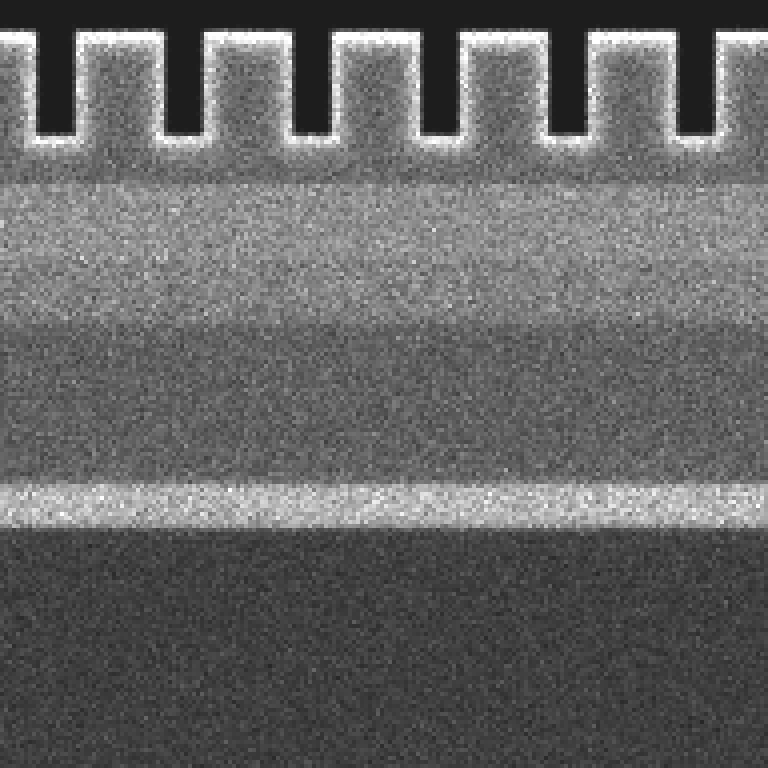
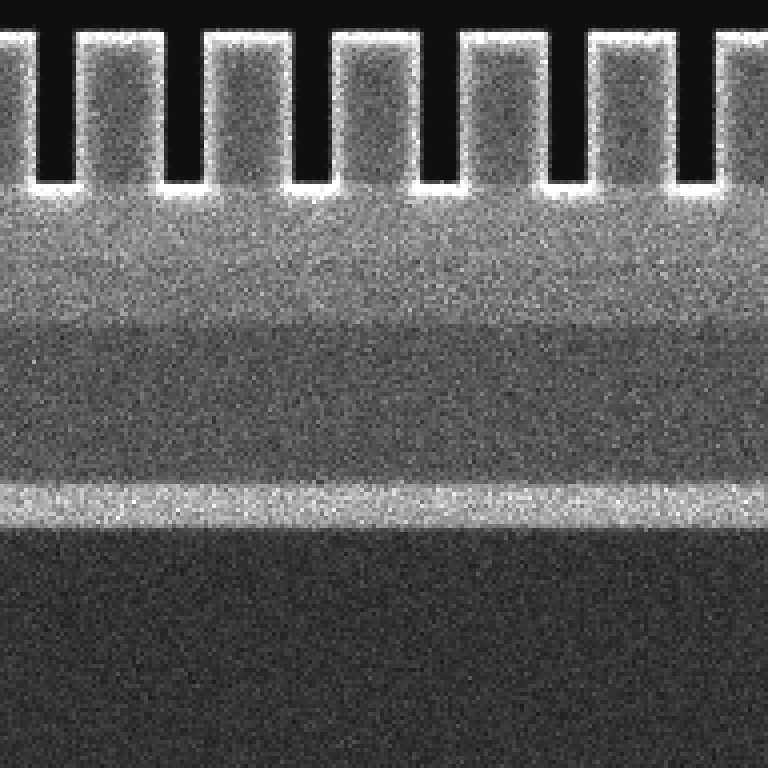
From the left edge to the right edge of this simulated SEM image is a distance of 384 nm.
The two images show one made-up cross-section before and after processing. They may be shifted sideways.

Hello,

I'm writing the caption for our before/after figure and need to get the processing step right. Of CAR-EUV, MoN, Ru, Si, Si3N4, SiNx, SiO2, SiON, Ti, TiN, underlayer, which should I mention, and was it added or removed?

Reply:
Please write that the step removed underlayer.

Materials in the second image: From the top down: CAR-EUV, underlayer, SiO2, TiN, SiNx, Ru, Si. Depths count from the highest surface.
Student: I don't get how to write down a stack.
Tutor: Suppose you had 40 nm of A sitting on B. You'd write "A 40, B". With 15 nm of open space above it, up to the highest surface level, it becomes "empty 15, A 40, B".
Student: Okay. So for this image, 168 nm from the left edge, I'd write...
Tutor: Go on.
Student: CAR-EUV 52, underlayer 24, SiO2 38, TiN 32, SiNx 80, Ru 22, Si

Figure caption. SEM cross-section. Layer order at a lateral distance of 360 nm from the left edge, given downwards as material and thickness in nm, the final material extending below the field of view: CAR-EUV 52, underlayer 24, SiO2 38, TiN 32, SiNx 80, Ru 22, Si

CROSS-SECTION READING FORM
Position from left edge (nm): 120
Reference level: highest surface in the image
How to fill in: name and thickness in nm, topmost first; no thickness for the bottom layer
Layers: CAR-EUV 52, underlayer 24, SiO2 38, TiN 32, SiNx 80, Ru 22, Si